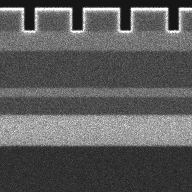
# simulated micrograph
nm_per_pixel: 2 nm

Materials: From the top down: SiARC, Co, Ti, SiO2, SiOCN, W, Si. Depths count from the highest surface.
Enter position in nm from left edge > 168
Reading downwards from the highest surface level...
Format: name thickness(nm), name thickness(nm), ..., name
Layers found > SiARC 46, Co 40, Ti 74, SiO2 18, SiOCN 36, W 62, Si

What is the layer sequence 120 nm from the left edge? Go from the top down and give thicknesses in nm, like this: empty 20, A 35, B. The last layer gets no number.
SiARC 46, Co 40, Ti 74, SiO2 18, SiOCN 36, W 62, Si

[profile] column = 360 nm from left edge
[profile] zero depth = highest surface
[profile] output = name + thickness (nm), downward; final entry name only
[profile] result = SiARC 46, Co 40, Ti 74, SiO2 18, SiOCN 36, W 62, Si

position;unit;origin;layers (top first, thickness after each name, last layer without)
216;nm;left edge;SiARC 46, Co 40, Ti 74, SiO2 18, SiOCN 36, W 62, Si